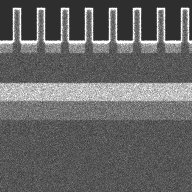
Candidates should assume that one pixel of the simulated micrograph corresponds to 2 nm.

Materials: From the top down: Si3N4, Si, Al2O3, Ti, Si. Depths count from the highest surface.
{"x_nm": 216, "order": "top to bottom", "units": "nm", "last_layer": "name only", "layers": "empty 66, Si3N4 24, Si 60, Al2O3 36, Ti 38, Si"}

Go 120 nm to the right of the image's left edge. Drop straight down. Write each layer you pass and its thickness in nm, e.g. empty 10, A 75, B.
empty 66, Si3N4 24, Si 60, Al2O3 36, Ti 38, Si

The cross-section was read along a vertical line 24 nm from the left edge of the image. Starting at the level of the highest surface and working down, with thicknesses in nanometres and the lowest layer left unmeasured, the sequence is empty 66, Si3N4 24, Si 60, Al2O3 36, Ti 38, Si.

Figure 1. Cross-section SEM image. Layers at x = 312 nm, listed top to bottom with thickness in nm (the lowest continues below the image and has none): empty 66, Si3N4 24, Si 60, Al2O3 36, Ti 38, Si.